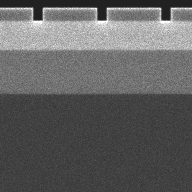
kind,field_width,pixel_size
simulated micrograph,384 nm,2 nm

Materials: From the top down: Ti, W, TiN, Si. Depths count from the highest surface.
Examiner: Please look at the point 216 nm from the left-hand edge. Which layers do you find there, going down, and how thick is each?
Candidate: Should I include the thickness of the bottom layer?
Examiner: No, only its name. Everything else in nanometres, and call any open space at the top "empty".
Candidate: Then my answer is Ti 26, W 58, TiN 88, Si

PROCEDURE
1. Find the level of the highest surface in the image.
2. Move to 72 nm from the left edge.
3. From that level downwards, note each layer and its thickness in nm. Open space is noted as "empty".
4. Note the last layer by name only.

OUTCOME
empty 26, W 58, TiN 88, Si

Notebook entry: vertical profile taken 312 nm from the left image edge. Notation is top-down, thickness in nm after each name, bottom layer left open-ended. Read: Ti 26, W 58, TiN 88, Si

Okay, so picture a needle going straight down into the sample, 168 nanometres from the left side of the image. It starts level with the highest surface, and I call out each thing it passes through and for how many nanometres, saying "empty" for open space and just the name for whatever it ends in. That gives Ti 26, W 58, TiN 88, Si